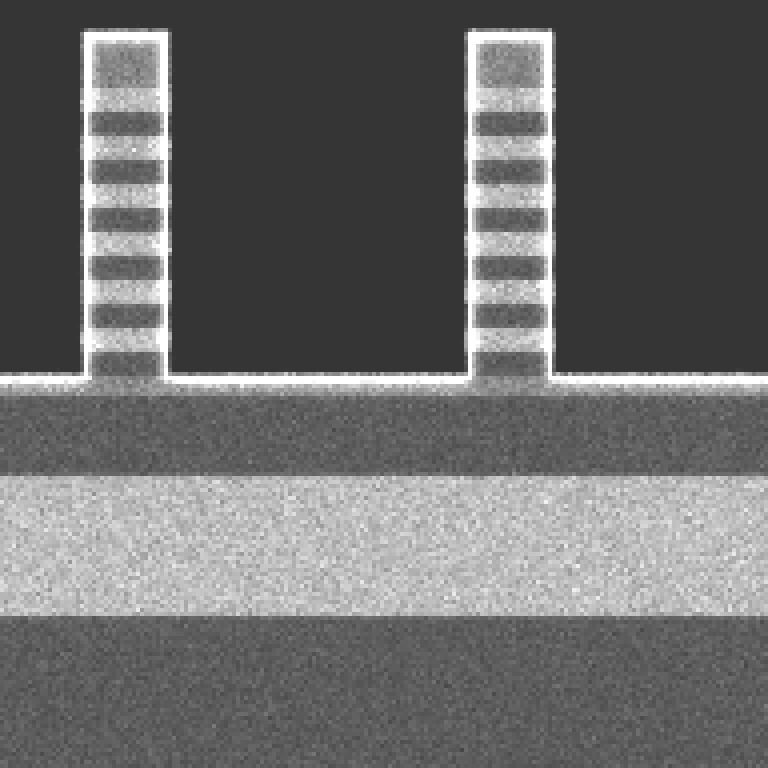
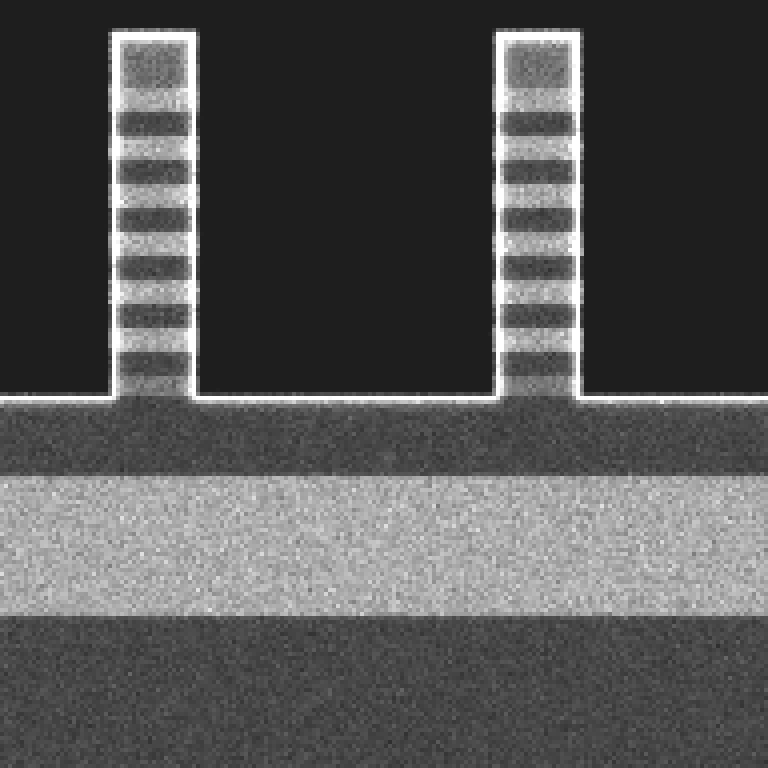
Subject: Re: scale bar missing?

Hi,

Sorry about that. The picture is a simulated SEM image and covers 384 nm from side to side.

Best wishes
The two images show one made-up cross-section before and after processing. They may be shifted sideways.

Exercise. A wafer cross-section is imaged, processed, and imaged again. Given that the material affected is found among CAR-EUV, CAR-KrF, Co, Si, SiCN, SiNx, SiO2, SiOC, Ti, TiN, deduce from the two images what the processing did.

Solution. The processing removed TiN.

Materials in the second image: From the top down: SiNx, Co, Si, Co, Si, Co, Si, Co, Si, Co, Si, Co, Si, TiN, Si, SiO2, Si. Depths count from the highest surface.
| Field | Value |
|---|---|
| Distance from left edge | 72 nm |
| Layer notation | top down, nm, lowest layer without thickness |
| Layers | SiNx 28, Co 12, Si 12, Co 12, Si 12, Co 12, Si 12, Co 12, Si 12, Co 12, Si 12, Co 12, Si 12, TiN 10, Si 40, SiO2 70, Si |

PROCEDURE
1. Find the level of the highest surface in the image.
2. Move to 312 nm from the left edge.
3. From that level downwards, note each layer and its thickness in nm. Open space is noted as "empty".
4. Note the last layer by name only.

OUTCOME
empty 182, Si 40, SiO2 70, Si